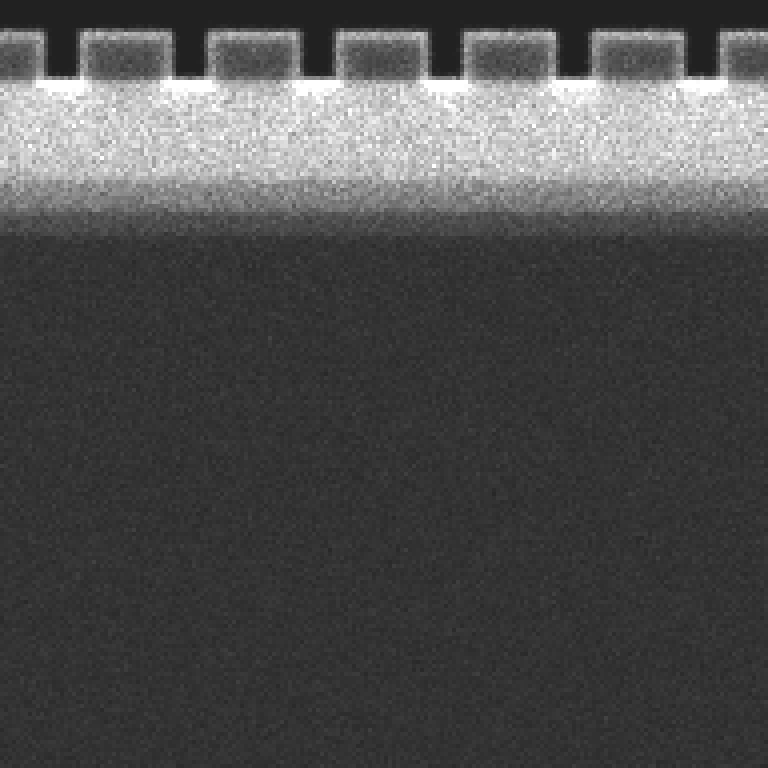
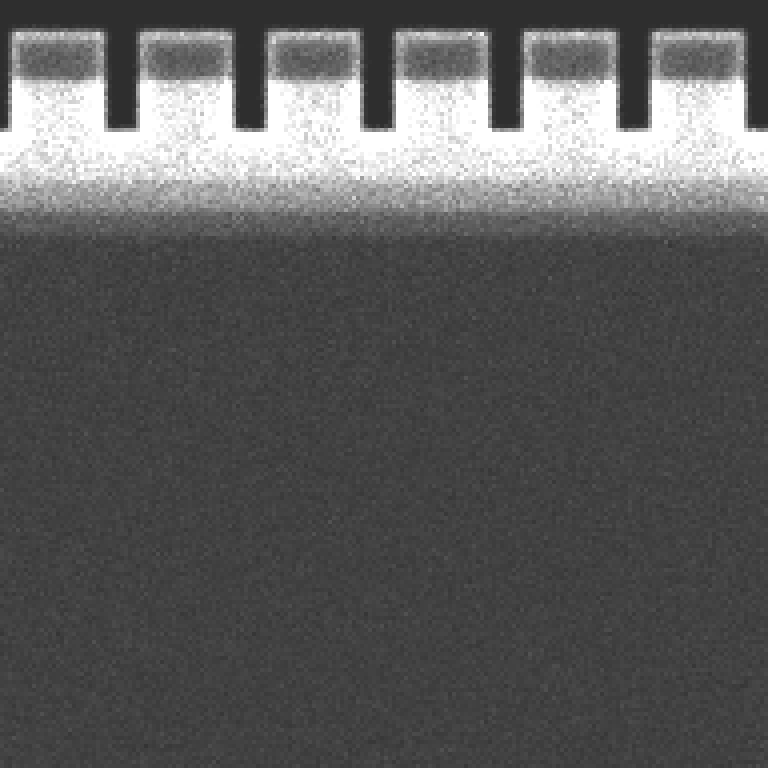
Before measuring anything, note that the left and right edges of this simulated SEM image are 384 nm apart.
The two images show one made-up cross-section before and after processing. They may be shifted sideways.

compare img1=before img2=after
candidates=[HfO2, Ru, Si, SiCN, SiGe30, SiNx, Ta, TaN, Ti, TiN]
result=removed:HfO2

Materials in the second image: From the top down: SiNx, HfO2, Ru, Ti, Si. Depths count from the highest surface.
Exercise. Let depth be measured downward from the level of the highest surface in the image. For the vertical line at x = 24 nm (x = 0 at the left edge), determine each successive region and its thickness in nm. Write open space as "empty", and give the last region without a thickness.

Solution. SiNx 24, HfO2 50, Ru 16, Ti 12, Si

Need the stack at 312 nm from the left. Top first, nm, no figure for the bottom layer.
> empty 50, HfO2 24, Ru 16, Ti 12, Si